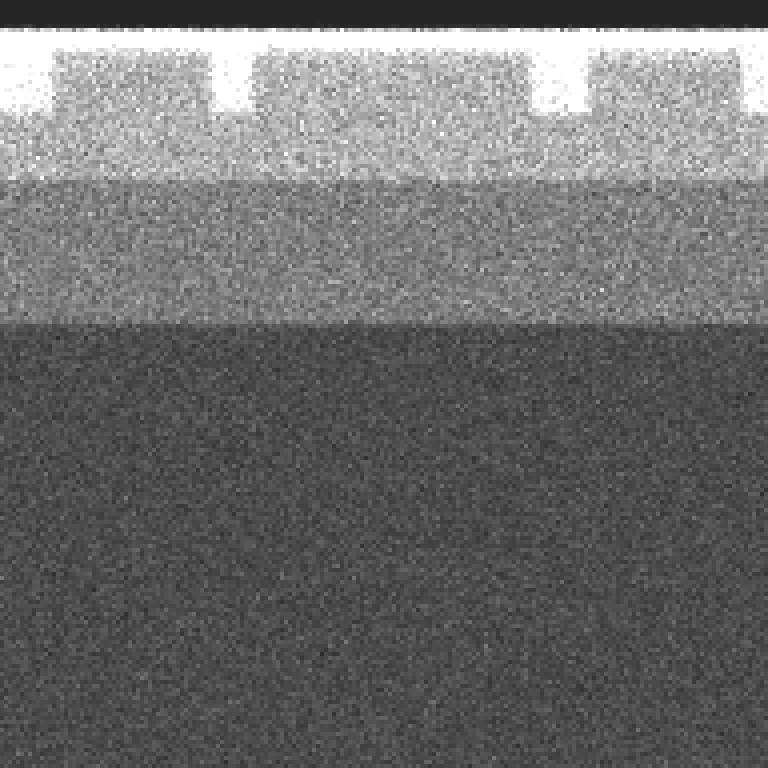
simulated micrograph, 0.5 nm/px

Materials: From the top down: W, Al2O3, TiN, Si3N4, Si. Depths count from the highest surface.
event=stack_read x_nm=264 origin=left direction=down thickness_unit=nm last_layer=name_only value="Al2O3 74, TiN 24, Si3N4 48, Si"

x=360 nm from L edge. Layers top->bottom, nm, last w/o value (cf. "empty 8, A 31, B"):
Al2O3 74, TiN 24, Si3N4 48, Si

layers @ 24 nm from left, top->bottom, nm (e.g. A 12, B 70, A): W 40, Al2O3 34, TiN 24, Si3N4 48, Si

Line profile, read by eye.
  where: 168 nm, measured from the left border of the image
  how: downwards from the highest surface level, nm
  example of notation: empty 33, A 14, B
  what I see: Al2O3 74, TiN 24, Si3N4 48, Si